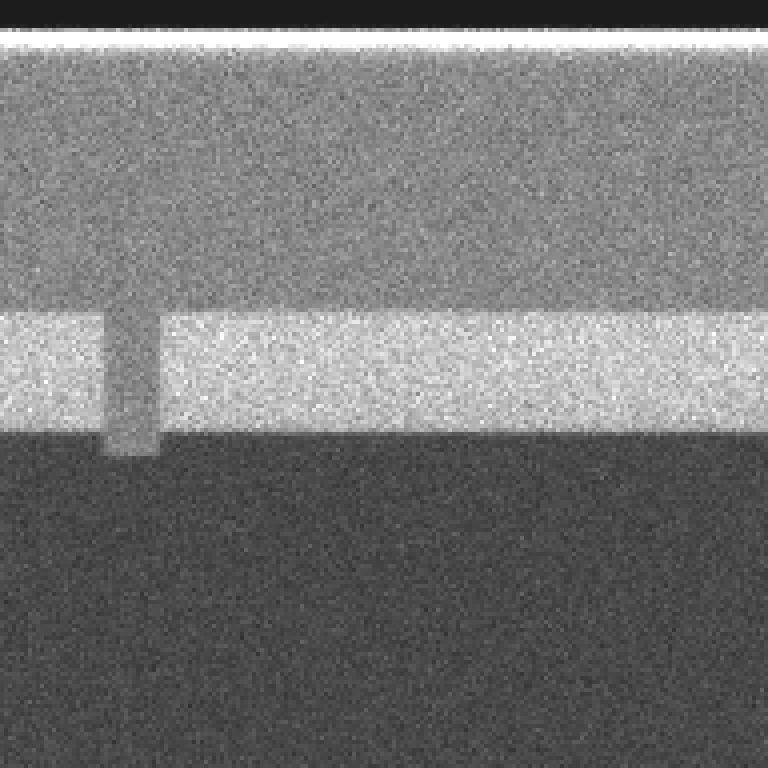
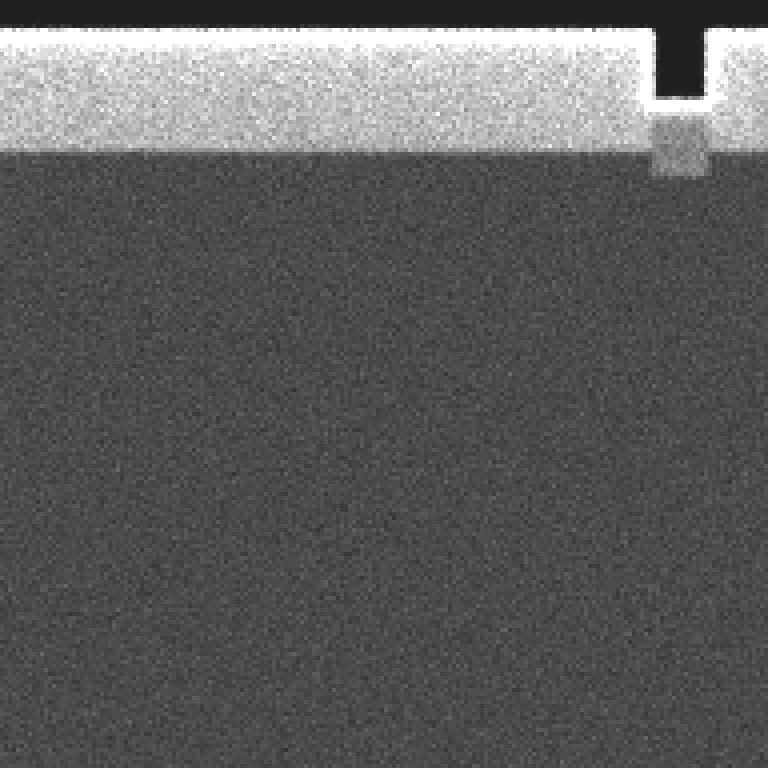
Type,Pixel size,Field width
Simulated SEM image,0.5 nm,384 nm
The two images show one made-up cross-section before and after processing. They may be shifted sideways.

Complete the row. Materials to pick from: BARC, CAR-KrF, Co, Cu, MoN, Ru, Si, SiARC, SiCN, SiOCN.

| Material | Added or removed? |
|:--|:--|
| SiARC | removed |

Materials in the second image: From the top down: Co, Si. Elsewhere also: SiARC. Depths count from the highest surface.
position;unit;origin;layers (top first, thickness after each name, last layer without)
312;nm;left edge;Co 60, Si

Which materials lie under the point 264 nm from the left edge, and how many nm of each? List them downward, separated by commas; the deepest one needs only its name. Co 60, Si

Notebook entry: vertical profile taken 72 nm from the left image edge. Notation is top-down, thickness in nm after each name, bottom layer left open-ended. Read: Co 60, Si